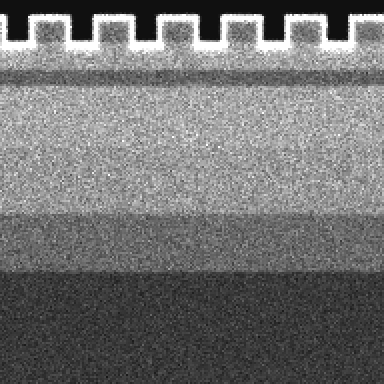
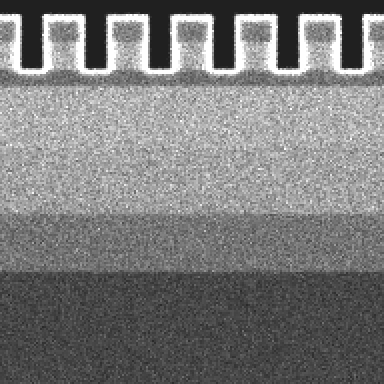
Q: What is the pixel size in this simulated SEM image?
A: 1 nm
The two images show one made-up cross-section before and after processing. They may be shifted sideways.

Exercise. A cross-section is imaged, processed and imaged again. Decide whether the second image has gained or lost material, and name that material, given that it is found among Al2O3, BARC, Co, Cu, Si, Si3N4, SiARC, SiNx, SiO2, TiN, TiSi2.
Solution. removed: SiO2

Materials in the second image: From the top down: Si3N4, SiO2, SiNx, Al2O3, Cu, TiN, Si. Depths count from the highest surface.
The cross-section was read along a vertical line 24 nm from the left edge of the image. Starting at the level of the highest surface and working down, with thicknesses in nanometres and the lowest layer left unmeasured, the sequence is empty 54, SiNx 16, Al2O3 62, Cu 66, TiN 58, Si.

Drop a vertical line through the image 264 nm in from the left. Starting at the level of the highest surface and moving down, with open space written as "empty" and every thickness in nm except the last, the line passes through Si3N4 26, SiO2 28, SiNx 16, Al2O3 62, Cu 66, TiN 58, Si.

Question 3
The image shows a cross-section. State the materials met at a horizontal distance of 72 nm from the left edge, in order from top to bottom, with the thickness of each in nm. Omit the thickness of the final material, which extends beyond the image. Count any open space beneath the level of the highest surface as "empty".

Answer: Si3N4 26, SiO2 28, SiNx 16, Al2O3 62, Cu 66, TiN 58, Si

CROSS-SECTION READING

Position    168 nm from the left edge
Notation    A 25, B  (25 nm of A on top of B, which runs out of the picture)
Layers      empty 54, SiNx 16, Al2O3 62, Cu 66, TiN 58, Si